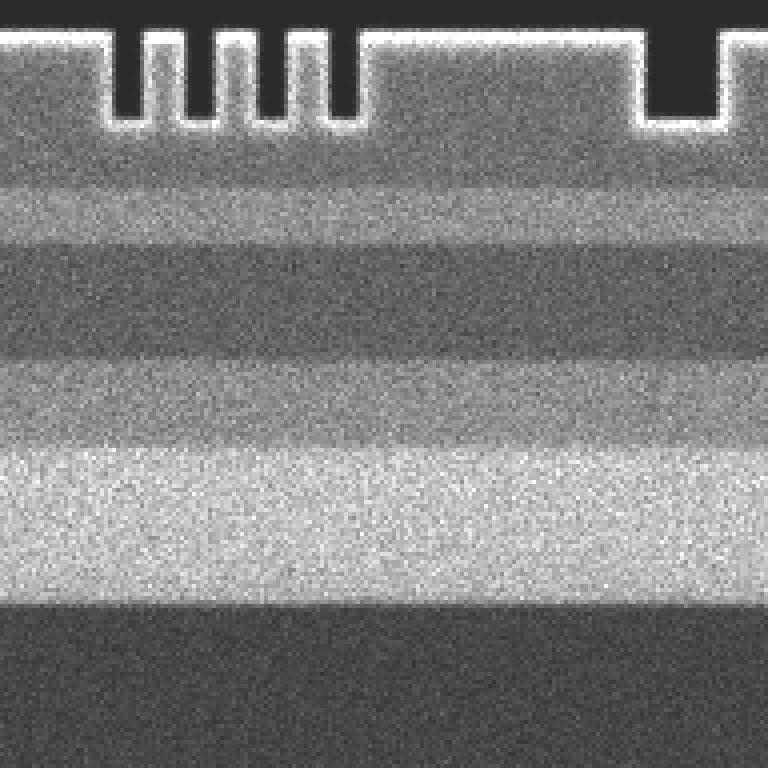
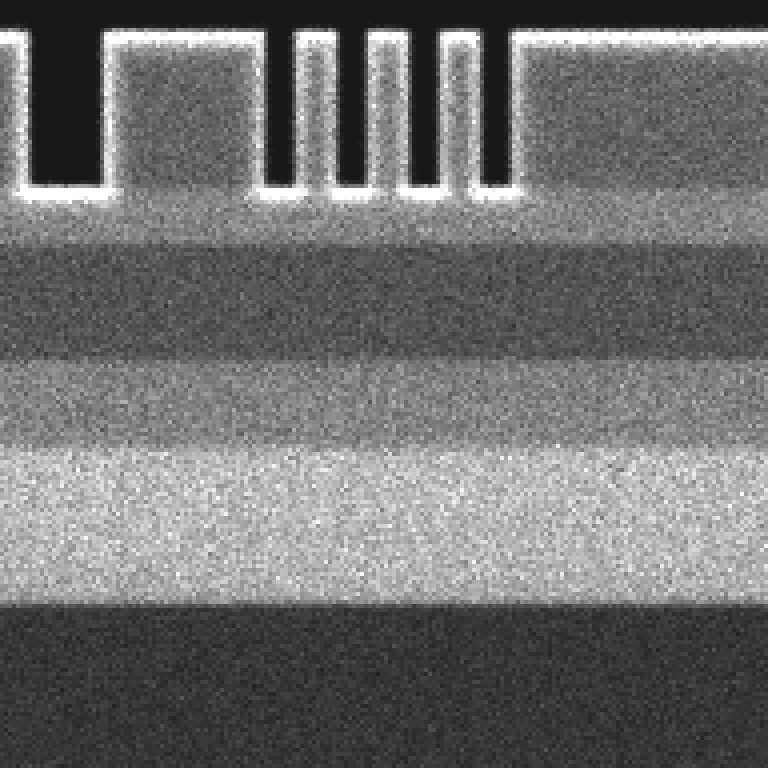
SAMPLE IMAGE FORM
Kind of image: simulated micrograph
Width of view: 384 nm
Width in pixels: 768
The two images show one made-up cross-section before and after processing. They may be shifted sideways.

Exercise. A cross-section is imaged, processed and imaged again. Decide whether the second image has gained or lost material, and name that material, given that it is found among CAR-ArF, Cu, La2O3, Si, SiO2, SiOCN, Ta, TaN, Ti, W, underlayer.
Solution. removed: underlayer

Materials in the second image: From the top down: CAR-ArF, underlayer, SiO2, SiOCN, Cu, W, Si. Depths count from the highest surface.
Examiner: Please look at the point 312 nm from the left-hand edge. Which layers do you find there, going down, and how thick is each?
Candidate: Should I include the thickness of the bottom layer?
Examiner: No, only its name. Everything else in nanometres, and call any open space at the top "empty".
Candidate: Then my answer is CAR-ArF 44, underlayer 34, SiO2 28, SiOCN 58, Cu 44, W 78, Si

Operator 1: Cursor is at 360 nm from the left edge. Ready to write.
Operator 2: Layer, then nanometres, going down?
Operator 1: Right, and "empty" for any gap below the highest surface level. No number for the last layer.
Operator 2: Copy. CAR-ArF 44, underlayer 34, SiO2 28, SiOCN 58, Cu 44, W 78, Si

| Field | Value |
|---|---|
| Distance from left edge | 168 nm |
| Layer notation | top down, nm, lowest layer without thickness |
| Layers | empty 78, SiO2 28, SiOCN 58, Cu 44, W 78, Si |